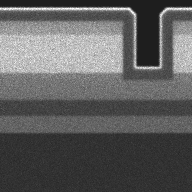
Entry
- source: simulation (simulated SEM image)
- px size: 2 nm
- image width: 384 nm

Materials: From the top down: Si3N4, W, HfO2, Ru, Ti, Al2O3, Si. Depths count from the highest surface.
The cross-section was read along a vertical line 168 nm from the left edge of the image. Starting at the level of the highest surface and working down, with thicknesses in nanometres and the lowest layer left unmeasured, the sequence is Si3N4 26, W 28, HfO2 76, Ru 54, Ti 32, Al2O3 34, Si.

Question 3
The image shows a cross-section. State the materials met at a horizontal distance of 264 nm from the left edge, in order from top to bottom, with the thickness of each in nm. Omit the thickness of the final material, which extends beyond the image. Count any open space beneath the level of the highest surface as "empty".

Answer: empty 6, Si3N4 138, Ru 40, Ti 32, Al2O3 34, Si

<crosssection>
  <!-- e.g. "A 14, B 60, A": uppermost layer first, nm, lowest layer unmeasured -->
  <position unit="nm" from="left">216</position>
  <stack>Si3N4 26, W 28, HfO2 76, Ru 54, Ti 32, Al2O3 34, Si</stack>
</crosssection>